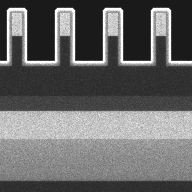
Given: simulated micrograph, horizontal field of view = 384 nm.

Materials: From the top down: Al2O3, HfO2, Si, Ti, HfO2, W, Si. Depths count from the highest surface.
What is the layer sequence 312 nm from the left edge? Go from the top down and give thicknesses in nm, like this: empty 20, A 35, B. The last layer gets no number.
Al2O3 10, HfO2 46, Si 120, Ti 30, HfO2 56, W 84, Si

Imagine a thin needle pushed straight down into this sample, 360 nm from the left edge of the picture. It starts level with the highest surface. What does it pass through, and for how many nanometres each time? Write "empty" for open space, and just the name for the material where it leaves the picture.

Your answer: empty 106, Al2O3 10, Si 60, Ti 30, HfO2 56, W 84, Si